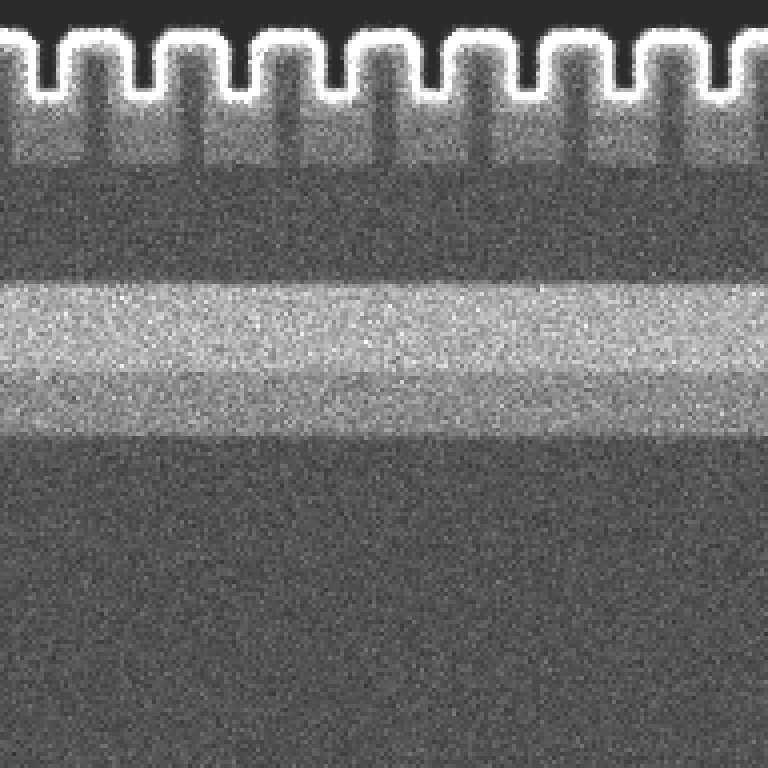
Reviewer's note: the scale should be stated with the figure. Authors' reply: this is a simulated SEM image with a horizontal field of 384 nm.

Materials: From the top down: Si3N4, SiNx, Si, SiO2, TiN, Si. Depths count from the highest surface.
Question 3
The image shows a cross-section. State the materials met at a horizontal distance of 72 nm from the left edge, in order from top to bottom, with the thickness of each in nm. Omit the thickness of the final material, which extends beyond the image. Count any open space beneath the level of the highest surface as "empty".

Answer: empty 30, Si3N4 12, SiNx 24, Si 60, SiO2 44, TiN 32, Si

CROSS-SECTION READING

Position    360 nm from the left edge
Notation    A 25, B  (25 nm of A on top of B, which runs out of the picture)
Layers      empty 30, Si3N4 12, SiNx 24, Si 60, SiO2 44, TiN 32, Si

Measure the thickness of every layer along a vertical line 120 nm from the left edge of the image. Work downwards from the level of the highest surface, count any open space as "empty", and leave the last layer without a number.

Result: empty 30, Si3N4 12, SiNx 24, Si 60, SiO2 44, TiN 32, Si